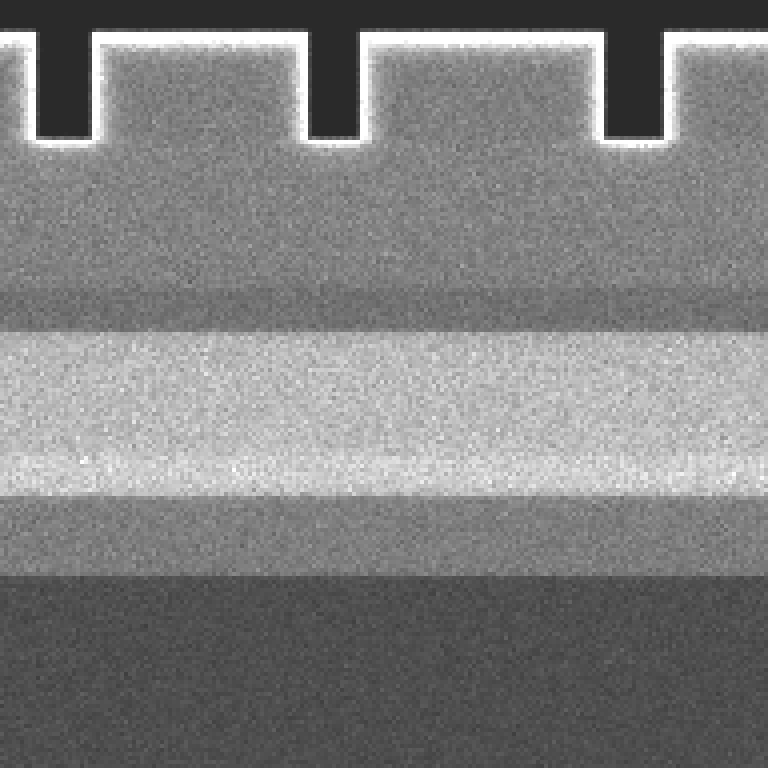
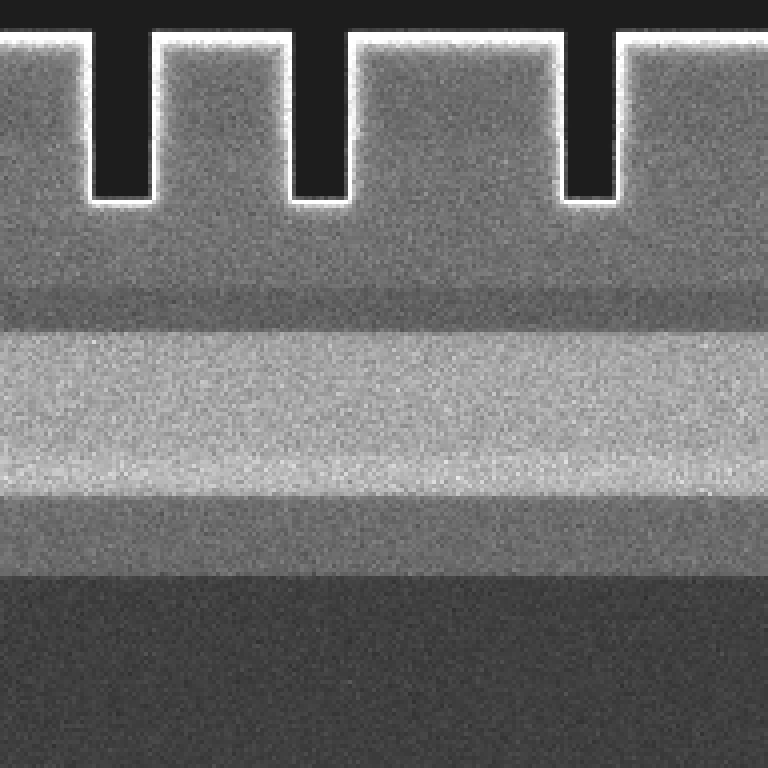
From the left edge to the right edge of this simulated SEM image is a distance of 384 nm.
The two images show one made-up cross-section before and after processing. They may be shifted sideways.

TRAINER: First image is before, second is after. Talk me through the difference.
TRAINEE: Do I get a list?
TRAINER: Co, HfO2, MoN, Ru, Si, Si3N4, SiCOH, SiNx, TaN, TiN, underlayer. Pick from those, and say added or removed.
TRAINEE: removed: TiN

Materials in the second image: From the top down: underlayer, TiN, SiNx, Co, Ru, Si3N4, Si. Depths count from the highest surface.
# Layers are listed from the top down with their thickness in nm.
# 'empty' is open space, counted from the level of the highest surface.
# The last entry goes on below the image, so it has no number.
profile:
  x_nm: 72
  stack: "empty 84, TiN 44, SiNx 22, Co 62, Ru 20, Si3N4 40, Si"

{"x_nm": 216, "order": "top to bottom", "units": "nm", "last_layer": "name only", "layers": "underlayer 54, TiN 74, SiNx 22, Co 62, Ru 20, Si3N4 40, Si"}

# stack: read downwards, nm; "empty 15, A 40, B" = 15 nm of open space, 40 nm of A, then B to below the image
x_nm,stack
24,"underlayer 54, TiN 74, SiNx 22, Co 62, Ru 20, Si3N4 40, Si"